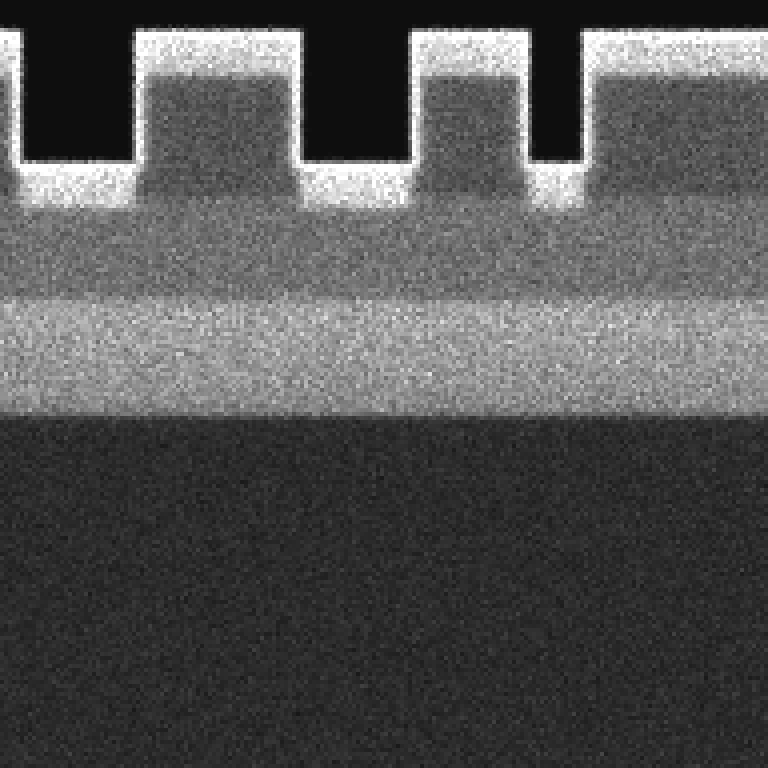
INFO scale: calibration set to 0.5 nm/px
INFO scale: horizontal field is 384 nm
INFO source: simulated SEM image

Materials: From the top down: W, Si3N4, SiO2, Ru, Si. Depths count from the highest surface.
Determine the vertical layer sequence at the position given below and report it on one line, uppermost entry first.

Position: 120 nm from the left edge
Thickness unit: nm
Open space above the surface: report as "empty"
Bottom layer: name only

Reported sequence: W 22, Si3N4 60, SiO2 52, Ru 58, Si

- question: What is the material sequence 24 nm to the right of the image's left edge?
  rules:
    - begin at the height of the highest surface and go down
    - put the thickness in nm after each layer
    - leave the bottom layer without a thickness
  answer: empty 66, W 22, SiO2 46, Ru 58, Si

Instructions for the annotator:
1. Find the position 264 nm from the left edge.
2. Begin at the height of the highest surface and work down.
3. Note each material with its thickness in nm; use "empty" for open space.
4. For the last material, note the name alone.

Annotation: empty 66, W 22, SiO2 46, Ru 58, Si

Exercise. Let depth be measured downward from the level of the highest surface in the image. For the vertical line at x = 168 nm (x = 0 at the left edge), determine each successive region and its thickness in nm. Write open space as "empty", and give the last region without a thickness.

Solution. empty 66, W 22, SiO2 46, Ru 58, Si